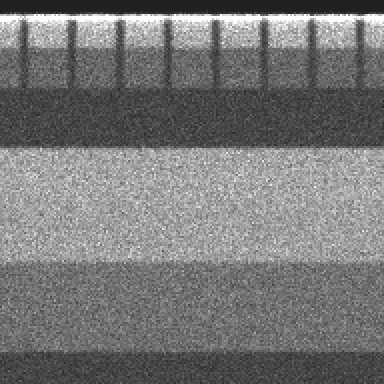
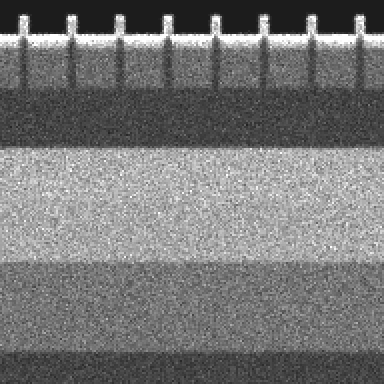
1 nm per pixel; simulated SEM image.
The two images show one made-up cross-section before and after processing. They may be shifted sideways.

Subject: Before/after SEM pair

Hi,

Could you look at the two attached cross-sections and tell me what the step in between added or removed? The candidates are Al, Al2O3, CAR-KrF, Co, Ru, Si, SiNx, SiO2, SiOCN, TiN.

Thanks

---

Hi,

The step removed Ru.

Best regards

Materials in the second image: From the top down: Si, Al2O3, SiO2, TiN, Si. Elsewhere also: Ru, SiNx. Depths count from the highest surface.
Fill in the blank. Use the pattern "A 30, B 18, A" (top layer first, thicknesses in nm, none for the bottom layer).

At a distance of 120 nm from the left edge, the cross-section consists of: Si 132, Al2O3 54, SiO2 60, TiN 90, Si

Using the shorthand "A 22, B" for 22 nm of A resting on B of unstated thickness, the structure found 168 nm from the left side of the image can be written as Si 132, Al2O3 54, SiO2 60, TiN 90, Si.